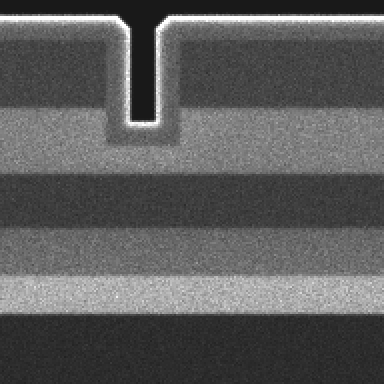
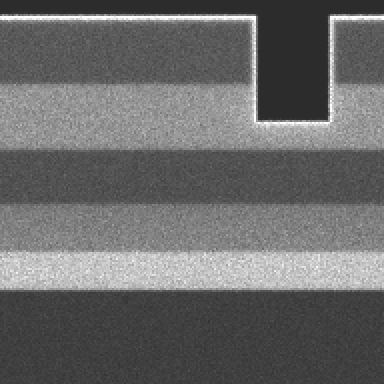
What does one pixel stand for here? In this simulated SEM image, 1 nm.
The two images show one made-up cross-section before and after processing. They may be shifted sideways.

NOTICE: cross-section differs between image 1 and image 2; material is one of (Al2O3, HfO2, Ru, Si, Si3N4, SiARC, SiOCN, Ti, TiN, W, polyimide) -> removed: Al2O3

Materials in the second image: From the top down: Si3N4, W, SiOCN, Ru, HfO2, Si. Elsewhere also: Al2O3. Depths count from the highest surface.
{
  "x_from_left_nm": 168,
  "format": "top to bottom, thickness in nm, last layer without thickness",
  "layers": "Si3N4 68, W 66, SiOCN 54, Ru 48, HfO2 38, Si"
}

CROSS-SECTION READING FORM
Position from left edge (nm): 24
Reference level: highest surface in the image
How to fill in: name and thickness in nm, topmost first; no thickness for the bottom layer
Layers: Si3N4 68, W 66, SiOCN 54, Ru 48, HfO2 38, Si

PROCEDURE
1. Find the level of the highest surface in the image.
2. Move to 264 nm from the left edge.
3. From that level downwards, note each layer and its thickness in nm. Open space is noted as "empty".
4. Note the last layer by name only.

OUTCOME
empty 106, W 28, SiOCN 54, Ru 48, HfO2 38, Si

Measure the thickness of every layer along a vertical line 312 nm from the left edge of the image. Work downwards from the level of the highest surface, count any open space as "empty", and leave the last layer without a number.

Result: empty 106, W 28, SiOCN 54, Ru 48, HfO2 38, Si